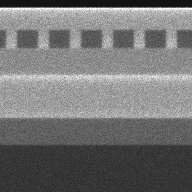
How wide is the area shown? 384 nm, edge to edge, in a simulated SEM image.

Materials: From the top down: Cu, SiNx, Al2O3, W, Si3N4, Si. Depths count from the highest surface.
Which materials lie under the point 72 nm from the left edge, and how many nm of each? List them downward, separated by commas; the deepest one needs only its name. Cu 44, SiNx 36, Al2O3 54, W 86, Si3N4 54, Si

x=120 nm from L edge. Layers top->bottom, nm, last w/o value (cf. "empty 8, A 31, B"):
Cu 44, SiNx 36, Al2O3 54, W 86, Si3N4 54, Si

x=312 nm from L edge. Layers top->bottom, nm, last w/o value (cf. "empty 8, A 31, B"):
Cu 44, SiNx 36, Al2O3 54, W 86, Si3N4 54, Si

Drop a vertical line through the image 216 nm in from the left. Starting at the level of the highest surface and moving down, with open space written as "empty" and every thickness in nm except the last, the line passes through Cu 80, Al2O3 54, W 86, Si3N4 54, Si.